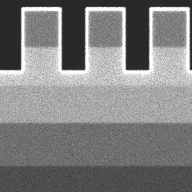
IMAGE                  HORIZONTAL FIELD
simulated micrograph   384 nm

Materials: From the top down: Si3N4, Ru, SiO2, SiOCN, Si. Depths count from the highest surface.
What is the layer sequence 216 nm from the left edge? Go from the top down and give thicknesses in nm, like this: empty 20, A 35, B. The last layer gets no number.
Si3N4 78, Ru 78, SiO2 74, SiOCN 86, Si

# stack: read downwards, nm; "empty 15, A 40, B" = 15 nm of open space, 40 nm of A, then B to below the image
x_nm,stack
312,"Si3N4 78, Ru 78, SiO2 74, SiOCN 86, Si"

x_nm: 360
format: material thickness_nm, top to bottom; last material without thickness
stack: Si3N4 78, Ru 78, SiO2 74, SiOCN 86, Si